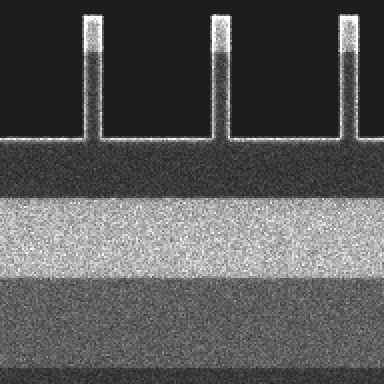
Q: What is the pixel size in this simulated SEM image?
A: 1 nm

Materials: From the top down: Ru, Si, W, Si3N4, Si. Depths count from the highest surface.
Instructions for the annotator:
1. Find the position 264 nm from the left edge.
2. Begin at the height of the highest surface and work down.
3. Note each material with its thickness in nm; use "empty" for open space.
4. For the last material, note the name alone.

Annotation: empty 122, Si 60, W 80, Si3N4 90, Si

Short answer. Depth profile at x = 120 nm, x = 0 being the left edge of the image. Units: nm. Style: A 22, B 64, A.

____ empty 122, Si 60, W 80, Si3N4 90, Si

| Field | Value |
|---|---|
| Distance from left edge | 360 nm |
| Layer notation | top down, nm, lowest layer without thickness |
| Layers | empty 122, Si 60, W 80, Si3N4 90, Si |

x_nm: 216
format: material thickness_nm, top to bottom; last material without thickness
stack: Ru 36, Si 146, W 80, Si3N4 90, Si